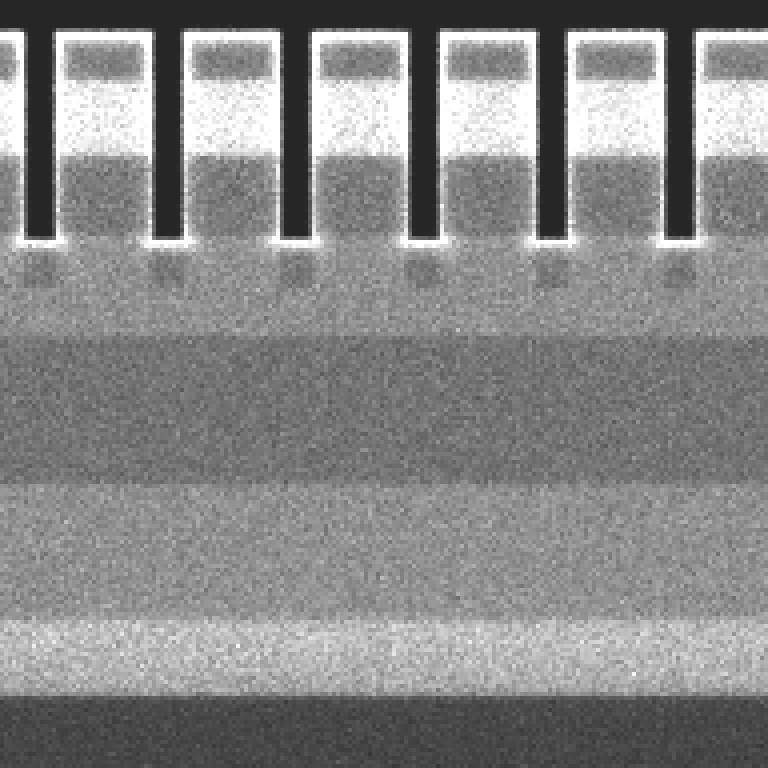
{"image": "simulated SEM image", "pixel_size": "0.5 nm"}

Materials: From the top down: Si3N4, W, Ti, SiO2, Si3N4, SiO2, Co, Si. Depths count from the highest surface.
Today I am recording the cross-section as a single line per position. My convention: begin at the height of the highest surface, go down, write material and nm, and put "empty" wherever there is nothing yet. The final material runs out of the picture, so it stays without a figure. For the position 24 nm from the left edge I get empty 104, Si3N4 24, SiO2 24, Si3N4 74, SiO2 68, Co 38, Si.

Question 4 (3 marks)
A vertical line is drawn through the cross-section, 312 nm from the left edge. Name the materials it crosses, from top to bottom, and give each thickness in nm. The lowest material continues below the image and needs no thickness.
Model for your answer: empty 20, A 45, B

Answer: Si3N4 24, W 38, Ti 40, SiO2 50, Si3N4 74, SiO2 68, Co 38, Si